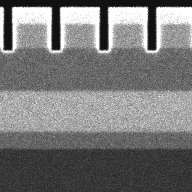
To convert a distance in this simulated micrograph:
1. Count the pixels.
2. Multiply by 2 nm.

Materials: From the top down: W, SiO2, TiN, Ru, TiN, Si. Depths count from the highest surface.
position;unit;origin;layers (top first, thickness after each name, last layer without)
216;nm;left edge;empty 86, TiN 80, Ru 82, TiN 34, Si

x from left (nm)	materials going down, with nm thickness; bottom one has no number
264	W 32, SiO2 48, TiN 86, Ru 82, TiN 34, Si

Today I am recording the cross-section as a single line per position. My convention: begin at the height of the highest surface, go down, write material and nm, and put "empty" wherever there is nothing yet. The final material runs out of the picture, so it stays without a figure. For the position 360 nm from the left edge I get W 32, SiO2 48, TiN 86, Ru 82, TiN 34, Si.